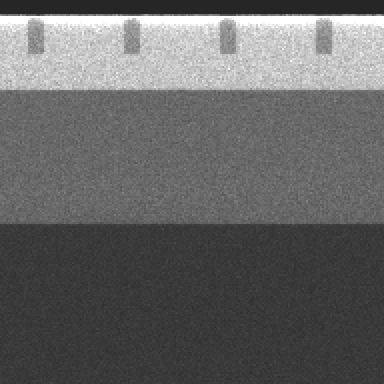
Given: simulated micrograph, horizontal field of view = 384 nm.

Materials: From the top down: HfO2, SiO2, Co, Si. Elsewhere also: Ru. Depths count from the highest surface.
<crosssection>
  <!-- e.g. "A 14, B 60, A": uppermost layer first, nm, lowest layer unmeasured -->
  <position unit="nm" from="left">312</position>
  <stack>HfO2 74, SiO2 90, Co 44, Si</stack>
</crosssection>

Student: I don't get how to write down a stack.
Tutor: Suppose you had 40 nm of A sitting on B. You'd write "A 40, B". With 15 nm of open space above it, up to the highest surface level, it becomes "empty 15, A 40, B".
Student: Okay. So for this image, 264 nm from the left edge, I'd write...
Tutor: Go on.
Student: HfO2 74, SiO2 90, Co 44, Si